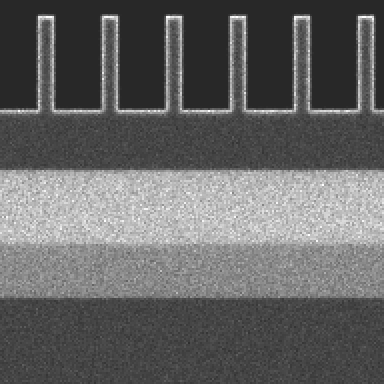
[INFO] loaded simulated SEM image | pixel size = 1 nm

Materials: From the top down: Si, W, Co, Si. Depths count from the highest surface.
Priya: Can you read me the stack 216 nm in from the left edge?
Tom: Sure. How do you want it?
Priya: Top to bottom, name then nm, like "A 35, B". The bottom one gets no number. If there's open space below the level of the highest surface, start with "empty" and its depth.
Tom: empty 94, Si 60, W 74, Co 54, Si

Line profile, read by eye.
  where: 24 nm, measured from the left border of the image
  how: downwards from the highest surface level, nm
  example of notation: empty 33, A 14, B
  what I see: empty 94, Si 60, W 74, Co 54, Si